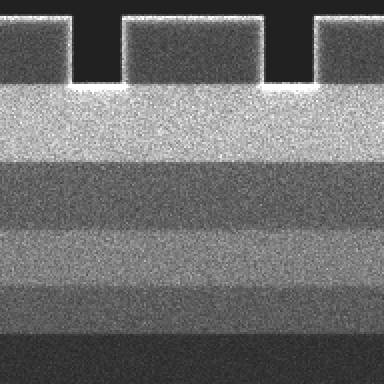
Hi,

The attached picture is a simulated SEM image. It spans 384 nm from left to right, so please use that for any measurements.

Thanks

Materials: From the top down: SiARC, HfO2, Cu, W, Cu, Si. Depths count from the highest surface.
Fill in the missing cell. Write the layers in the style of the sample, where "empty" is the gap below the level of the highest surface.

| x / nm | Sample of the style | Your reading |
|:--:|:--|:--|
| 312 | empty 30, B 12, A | empty 68, HfO2 78, Cu 68, W 56, Cu 48, Si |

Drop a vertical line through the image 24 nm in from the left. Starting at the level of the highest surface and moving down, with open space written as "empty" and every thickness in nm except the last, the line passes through SiARC 68, HfO2 78, Cu 68, W 56, Cu 48, Si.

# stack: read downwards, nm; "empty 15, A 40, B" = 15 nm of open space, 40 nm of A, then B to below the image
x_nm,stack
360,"SiARC 68, HfO2 78, Cu 68, W 56, Cu 48, Si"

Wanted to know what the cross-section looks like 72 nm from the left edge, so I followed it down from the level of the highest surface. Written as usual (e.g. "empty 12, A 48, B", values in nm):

empty 68, HfO2 78, Cu 68, W 56, Cu 48, Si